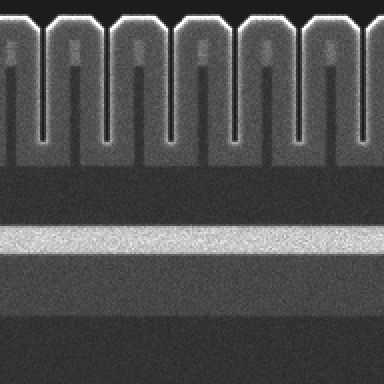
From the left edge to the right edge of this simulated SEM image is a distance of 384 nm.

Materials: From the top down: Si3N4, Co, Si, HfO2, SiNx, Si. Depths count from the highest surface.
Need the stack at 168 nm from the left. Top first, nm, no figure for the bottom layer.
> empty 126, Si3N4 24, Si 60, HfO2 28, SiNx 62, Si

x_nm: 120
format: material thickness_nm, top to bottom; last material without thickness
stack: empty 2, Si3N4 148, Si 60, HfO2 28, SiNx 62, Si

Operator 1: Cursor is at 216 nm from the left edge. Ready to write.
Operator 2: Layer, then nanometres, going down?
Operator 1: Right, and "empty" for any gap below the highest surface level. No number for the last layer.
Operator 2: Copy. Si3N4 150, Si 60, HfO2 28, SiNx 62, Si